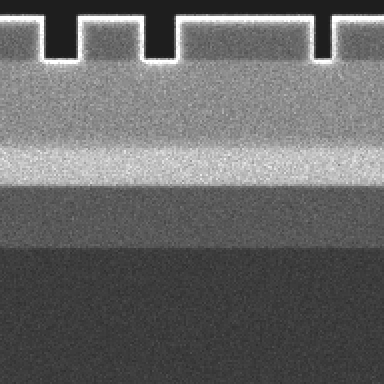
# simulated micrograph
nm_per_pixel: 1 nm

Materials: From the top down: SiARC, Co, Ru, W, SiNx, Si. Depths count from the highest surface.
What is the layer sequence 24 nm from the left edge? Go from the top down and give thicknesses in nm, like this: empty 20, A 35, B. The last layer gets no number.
SiARC 44, Co 80, Ru 8, W 38, SiNx 62, Si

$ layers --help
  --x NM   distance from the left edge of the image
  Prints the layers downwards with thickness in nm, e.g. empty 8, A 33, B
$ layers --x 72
empty 44, Co 80, Ru 8, W 38, SiNx 62, Si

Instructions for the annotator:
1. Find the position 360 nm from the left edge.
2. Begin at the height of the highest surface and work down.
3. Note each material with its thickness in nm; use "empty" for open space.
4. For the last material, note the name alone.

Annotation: SiARC 44, Co 80, Ru 8, W 38, SiNx 62, Si